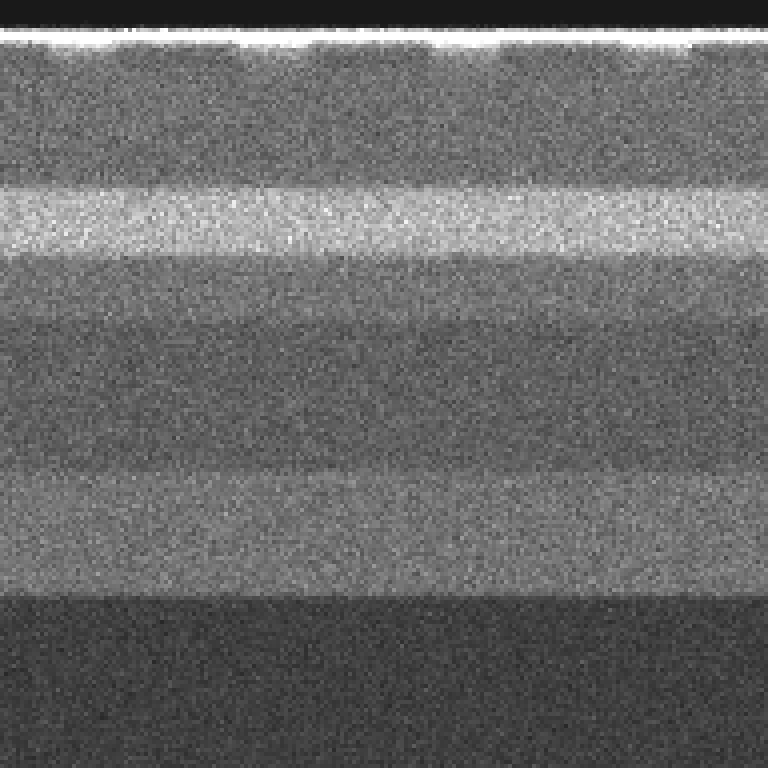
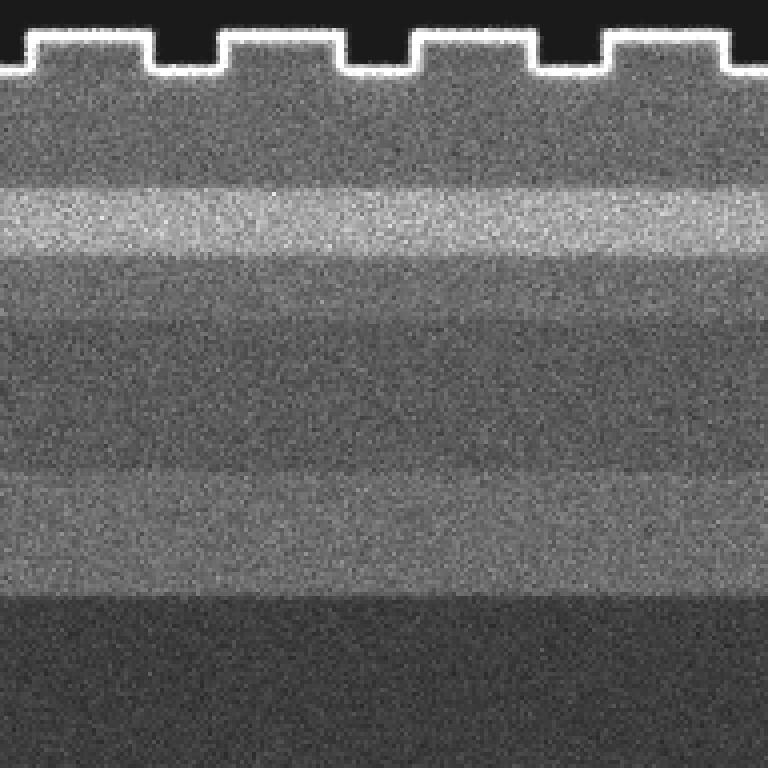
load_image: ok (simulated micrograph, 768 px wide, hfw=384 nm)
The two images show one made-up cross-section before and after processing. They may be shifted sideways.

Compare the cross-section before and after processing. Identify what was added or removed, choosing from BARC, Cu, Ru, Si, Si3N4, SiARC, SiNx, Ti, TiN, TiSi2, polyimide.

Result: SiARC removed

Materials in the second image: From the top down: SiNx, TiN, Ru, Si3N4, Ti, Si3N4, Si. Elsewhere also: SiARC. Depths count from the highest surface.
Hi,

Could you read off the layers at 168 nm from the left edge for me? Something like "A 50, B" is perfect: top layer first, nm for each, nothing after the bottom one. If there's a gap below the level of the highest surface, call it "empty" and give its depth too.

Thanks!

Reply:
SiNx 18, TiN 60, Ru 34, Si3N4 32, Ti 76, Si3N4 62, Si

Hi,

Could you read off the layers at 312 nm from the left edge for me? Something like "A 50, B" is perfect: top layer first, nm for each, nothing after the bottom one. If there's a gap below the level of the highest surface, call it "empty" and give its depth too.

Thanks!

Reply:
SiNx 18, TiN 60, Ru 34, Si3N4 32, Ti 76, Si3N4 62, Si